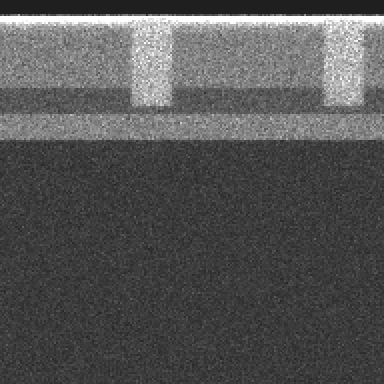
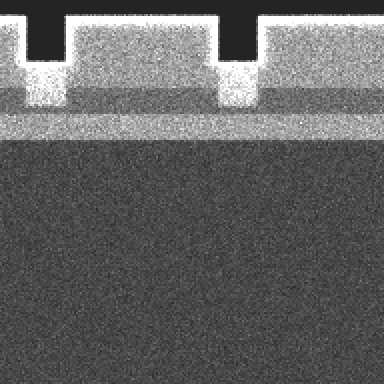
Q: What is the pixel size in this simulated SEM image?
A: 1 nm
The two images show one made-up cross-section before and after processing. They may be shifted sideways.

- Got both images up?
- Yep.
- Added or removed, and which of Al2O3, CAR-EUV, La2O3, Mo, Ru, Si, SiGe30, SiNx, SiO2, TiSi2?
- removed, Ru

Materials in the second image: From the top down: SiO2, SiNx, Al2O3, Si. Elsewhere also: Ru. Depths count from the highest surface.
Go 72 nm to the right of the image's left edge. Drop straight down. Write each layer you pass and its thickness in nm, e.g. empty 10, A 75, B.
SiO2 72, SiNx 26, Al2O3 26, Si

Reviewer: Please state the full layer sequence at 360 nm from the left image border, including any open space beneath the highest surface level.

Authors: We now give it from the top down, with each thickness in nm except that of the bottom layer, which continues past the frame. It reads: SiO2 72, SiNx 26, Al2O3 26, Si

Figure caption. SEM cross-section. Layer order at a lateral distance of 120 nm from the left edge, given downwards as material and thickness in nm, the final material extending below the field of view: SiO2 72, SiNx 26, Al2O3 26, Si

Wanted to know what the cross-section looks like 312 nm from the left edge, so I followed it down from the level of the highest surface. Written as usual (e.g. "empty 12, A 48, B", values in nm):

SiO2 72, SiNx 26, Al2O3 26, Si